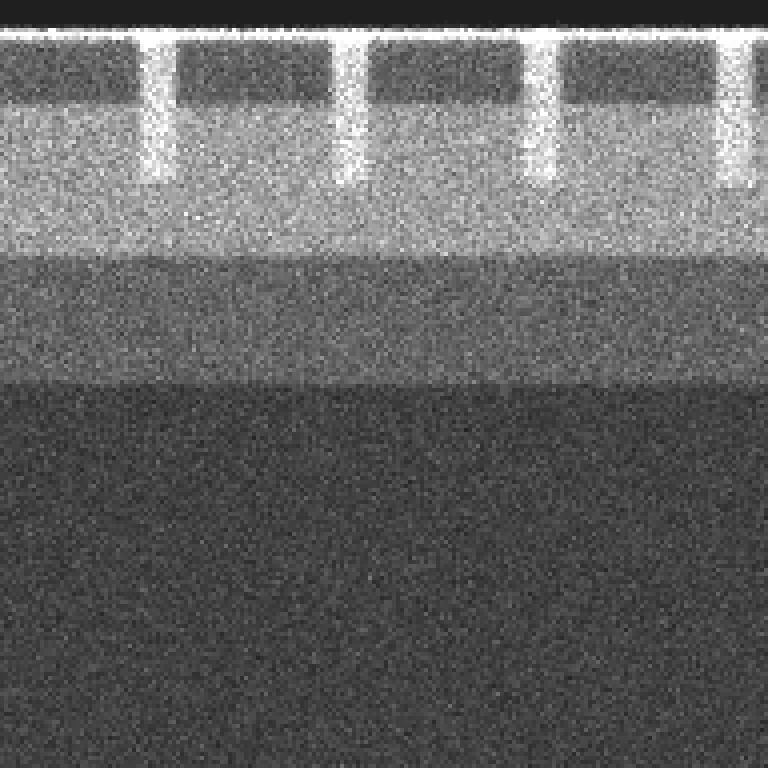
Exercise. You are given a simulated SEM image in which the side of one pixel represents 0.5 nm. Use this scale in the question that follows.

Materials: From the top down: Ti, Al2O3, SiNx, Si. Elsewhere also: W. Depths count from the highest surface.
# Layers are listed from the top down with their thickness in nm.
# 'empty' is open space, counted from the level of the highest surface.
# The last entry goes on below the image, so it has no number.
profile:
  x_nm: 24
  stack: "Ti 36, Al2O3 76, SiNx 64, Si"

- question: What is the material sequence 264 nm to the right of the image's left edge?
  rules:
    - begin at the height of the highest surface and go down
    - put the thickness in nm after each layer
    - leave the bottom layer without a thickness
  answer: W 76, Al2O3 36, SiNx 64, Si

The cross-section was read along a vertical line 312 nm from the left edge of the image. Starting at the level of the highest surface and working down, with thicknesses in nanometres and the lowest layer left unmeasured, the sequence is Ti 36, Al2O3 76, SiNx 64, Si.